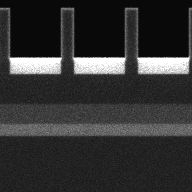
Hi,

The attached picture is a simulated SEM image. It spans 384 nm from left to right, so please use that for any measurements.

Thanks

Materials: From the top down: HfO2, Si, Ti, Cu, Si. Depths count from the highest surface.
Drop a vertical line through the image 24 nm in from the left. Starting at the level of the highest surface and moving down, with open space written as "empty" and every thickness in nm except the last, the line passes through empty 100, HfO2 32, Si 60, Ti 40, Cu 24, Si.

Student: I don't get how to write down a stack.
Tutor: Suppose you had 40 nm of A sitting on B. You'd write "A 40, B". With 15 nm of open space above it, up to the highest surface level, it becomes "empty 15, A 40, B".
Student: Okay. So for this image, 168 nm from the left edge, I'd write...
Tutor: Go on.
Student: empty 100, HfO2 32, Si 60, Ti 40, Cu 24, Si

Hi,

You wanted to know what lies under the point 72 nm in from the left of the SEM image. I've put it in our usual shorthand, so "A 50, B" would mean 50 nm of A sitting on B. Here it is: empty 100, HfO2 32, Si 60, Ti 40, Cu 24, Si